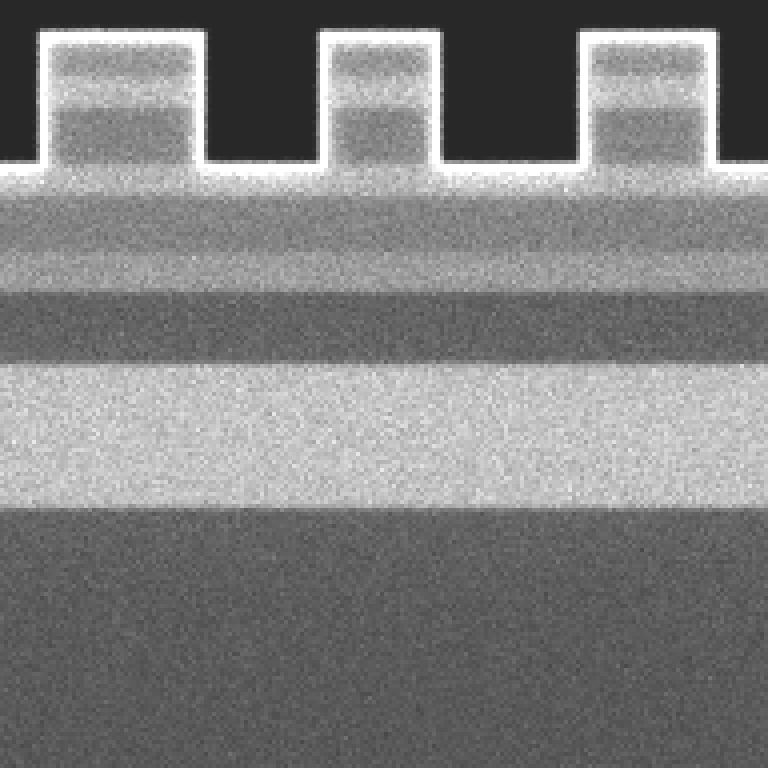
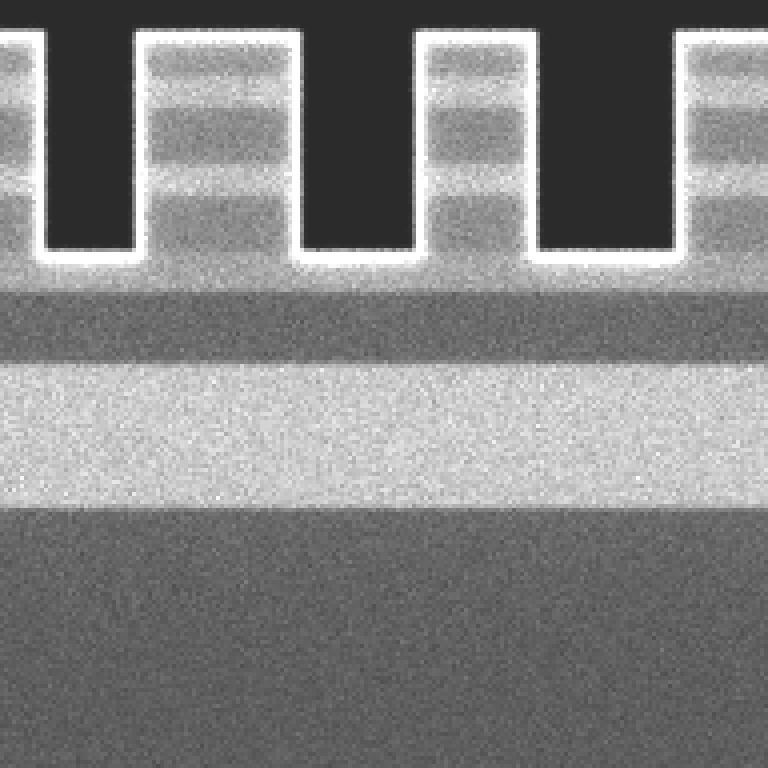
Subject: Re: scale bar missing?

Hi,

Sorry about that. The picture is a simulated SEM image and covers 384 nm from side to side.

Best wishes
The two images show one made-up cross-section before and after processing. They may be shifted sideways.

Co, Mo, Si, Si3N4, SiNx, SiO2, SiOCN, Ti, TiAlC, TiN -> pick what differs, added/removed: SiOCN and TiN removed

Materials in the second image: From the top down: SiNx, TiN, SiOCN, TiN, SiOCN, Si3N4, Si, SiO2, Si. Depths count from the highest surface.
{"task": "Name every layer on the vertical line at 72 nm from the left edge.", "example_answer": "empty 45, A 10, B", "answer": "SiNx 22, TiN 16, SiOCN 28, TiN 16, SiOCN 28, Si3N4 20, Si 36, SiO2 72, Si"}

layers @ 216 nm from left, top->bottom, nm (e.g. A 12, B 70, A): SiNx 22, TiN 16, SiOCN 28, TiN 16, SiOCN 28, Si3N4 20, Si 36, SiO2 72, Si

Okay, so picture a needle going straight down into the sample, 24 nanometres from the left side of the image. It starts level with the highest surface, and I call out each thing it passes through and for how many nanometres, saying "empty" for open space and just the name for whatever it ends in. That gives empty 110, Si3N4 20, Si 36, SiO2 72, Si